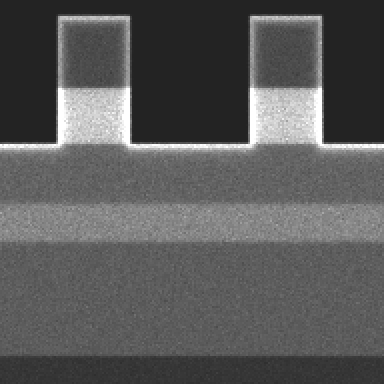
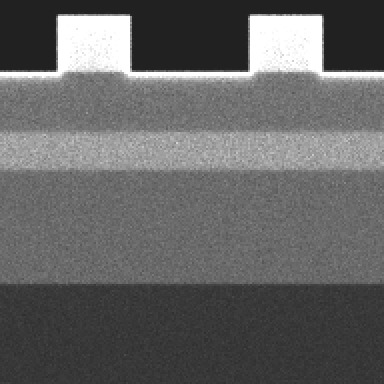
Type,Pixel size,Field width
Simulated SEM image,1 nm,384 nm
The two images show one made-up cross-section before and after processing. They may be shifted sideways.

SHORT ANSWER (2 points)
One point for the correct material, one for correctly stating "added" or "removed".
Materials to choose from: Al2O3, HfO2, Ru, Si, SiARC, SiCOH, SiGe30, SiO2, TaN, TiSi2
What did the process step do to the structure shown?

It removed SiARC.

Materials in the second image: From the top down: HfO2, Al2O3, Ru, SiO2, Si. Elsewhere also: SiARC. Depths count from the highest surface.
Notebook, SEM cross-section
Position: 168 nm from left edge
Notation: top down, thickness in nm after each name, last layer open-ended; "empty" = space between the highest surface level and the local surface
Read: empty 56, Al2O3 60, Ru 38, SiO2 114, Si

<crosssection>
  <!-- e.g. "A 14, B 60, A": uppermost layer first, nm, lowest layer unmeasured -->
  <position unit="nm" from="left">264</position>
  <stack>HfO2 56, Al2O3 60, Ru 38, SiO2 114, Si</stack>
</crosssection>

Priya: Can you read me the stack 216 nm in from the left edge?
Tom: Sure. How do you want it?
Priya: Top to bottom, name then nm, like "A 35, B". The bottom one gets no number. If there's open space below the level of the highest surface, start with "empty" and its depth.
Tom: empty 56, Al2O3 60, Ru 38, SiO2 114, Si